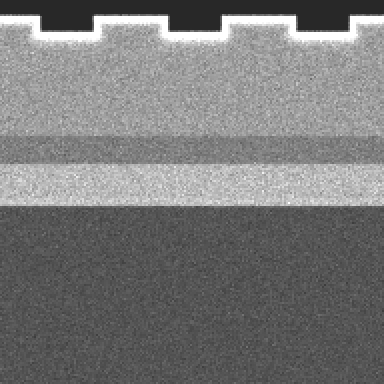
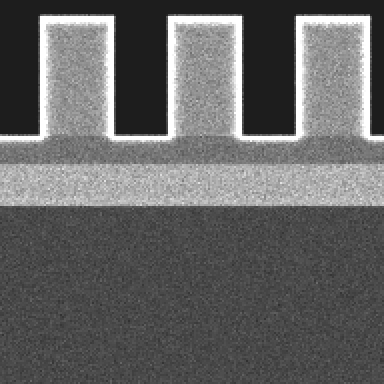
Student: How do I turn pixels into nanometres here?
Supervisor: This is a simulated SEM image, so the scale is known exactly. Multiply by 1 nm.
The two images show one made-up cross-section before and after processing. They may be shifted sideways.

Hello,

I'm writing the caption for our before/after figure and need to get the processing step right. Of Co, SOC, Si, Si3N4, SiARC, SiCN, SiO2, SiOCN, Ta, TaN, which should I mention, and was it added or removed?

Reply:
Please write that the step removed SOC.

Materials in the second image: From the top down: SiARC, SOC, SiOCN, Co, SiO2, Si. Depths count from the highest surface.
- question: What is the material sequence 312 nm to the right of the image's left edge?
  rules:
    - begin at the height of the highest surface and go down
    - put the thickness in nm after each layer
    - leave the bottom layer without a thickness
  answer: SiARC 16, SOC 104, SiOCN 28, Co 34, SiO2 8, Si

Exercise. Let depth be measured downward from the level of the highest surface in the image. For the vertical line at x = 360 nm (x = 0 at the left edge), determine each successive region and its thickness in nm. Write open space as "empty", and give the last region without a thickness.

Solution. SiARC 16, SOC 104, SiOCN 28, Co 34, SiO2 8, Si